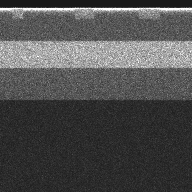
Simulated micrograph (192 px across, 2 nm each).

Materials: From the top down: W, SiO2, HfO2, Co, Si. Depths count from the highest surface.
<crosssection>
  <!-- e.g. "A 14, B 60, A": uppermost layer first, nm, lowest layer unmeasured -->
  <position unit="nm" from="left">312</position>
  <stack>W 22, SiO2 44, HfO2 54, Co 64, Si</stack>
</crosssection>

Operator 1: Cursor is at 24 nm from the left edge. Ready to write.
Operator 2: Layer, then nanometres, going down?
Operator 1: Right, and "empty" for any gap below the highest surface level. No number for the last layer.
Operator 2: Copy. SiO2 66, HfO2 54, Co 64, Si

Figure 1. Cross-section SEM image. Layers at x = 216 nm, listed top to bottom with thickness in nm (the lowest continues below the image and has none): SiO2 66, HfO2 54, Co 64, Si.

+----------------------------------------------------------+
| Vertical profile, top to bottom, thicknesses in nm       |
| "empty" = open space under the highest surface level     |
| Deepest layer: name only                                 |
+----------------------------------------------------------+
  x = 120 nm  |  SiO2 66, HfO2 54, Co 64, Si